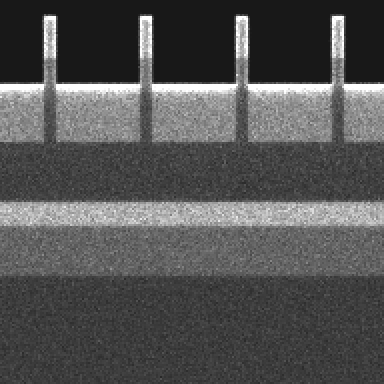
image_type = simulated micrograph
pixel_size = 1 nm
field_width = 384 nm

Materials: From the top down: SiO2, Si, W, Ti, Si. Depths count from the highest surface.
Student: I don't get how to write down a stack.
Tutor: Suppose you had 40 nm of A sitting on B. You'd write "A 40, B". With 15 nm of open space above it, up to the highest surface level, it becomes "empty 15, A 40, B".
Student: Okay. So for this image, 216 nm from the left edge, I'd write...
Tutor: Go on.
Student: empty 68, SiO2 58, Si 60, W 24, Ti 50, Si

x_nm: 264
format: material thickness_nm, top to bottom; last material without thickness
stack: empty 68, SiO2 58, Si 60, W 24, Ti 50, Si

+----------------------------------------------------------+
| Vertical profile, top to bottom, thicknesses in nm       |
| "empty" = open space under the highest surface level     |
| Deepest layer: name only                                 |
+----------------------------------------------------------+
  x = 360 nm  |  empty 68, SiO2 58, Si 60, W 24, Ti 50, Si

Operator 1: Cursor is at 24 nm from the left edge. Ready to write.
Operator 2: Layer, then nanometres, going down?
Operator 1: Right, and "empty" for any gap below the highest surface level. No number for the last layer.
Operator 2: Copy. empty 68, SiO2 58, Si 60, W 24, Ti 50, Si